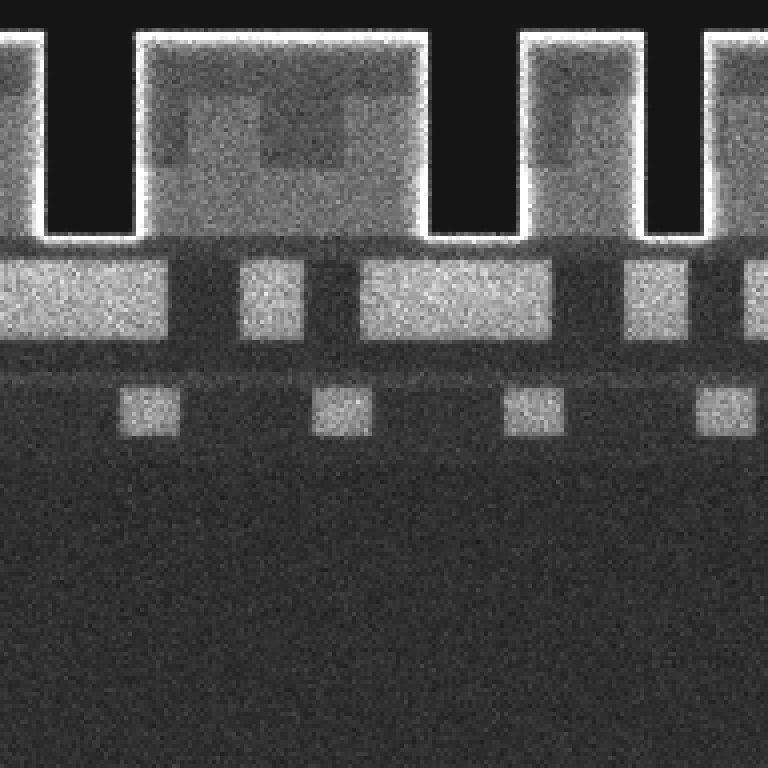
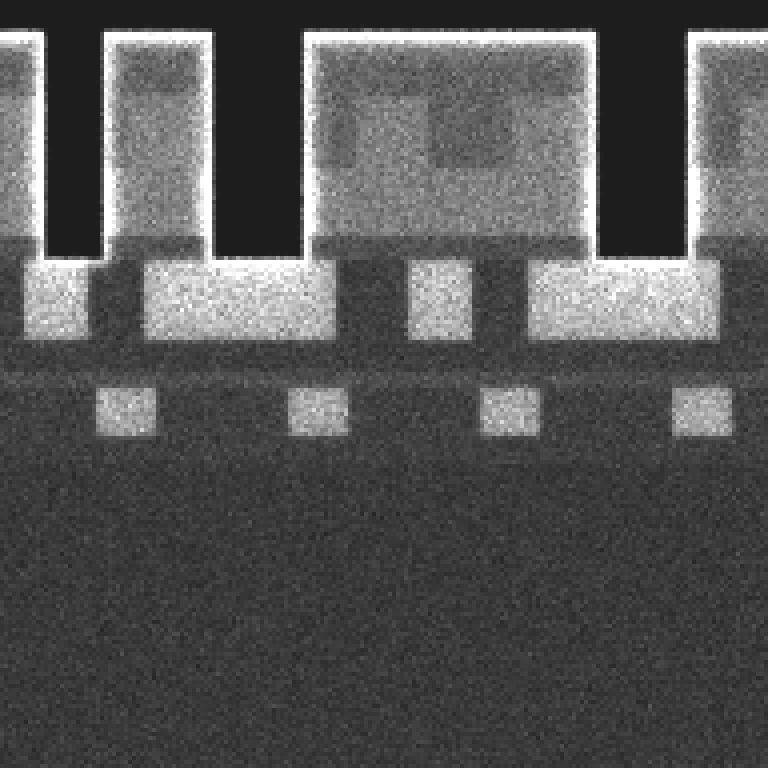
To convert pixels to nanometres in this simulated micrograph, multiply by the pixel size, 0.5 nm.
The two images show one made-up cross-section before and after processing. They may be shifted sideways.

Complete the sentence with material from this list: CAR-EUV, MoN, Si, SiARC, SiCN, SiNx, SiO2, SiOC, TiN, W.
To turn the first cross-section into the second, SiCN must be removed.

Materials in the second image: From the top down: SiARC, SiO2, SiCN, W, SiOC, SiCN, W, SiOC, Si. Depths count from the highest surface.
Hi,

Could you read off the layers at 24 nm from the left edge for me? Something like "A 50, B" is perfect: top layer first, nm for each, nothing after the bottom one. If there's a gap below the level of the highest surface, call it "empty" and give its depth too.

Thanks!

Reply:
empty 114, W 40, SiOC 16, SiCN 8, SiOC 38, Si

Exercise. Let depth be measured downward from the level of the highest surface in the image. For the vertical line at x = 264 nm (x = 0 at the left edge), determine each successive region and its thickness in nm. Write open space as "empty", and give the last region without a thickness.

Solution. SiARC 32, SiO2 70, SiCN 12, W 40, SiOC 16, SiCN 8, W 24, SiOC 14, Si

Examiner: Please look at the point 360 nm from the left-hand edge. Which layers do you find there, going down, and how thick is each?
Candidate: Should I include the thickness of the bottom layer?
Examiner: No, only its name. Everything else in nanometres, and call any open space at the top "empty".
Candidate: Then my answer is SiARC 68, SiO2 34, SiCN 12, SiOC 56, SiCN 8, W 24, SiOC 14, Si